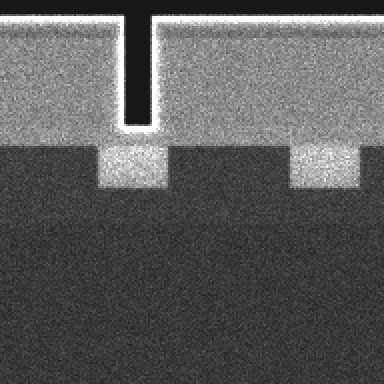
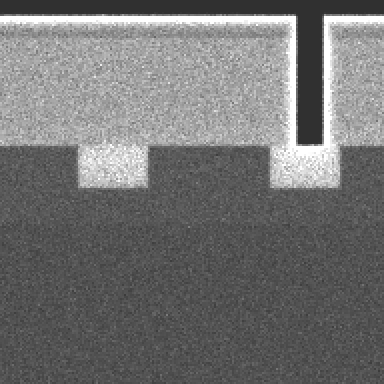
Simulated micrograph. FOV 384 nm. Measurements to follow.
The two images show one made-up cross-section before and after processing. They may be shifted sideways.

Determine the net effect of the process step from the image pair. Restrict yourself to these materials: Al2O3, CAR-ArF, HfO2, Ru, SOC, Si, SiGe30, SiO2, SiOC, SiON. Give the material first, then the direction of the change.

Al2O3: removed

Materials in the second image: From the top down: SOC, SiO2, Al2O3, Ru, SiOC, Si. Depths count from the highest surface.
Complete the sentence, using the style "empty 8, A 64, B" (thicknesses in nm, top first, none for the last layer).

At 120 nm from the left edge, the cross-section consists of SOC 22, SiO2 88, Al2O3 20, Ru 42, SiOC 36, Si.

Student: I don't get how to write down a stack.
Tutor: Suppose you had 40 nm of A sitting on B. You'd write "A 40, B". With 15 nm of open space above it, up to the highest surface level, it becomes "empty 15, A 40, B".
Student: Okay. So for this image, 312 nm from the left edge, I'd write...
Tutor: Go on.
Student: empty 130, Ru 42, SiOC 36, Si